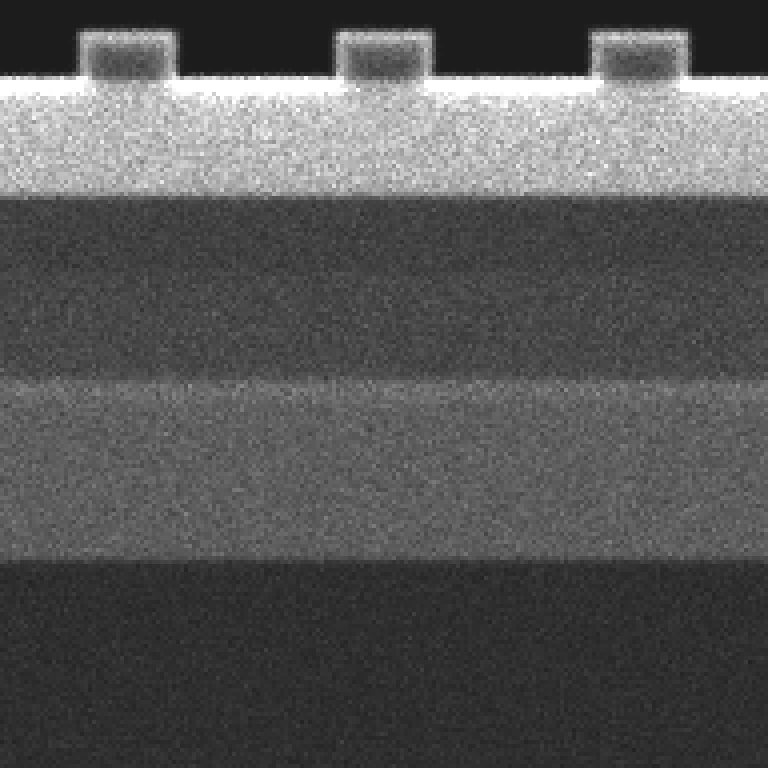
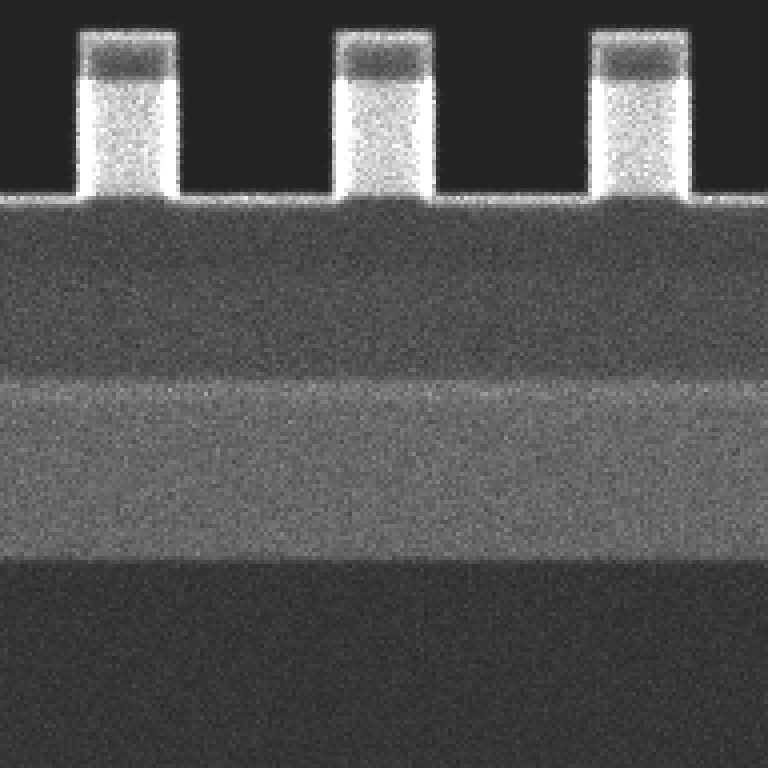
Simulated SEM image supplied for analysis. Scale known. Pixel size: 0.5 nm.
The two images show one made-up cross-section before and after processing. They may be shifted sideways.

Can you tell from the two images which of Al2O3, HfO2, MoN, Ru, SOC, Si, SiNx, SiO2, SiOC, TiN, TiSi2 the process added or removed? Yes, it removed HfO2.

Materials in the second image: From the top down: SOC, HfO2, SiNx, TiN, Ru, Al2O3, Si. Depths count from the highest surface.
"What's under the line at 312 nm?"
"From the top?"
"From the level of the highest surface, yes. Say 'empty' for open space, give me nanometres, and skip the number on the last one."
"SOC 24, HfO2 58, SiNx 38, TiN 54, Ru 10, Al2O3 80, Si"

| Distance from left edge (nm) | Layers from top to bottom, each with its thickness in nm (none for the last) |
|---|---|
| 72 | SOC 24, HfO2 58, SiNx 38, TiN 54, Ru 10, Al2O3 80, Si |